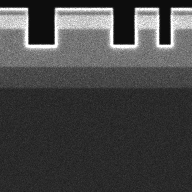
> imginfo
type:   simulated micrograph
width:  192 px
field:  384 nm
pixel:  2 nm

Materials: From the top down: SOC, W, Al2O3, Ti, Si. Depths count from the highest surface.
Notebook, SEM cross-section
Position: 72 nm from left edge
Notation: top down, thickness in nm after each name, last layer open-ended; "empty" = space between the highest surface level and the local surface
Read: empty 74, Al2O3 44, Ti 42, Si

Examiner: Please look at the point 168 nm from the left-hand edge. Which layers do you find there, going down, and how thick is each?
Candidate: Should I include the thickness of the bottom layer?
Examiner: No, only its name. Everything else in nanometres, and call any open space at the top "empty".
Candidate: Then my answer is SOC 14, W 28, Al2O3 76, Ti 42, Si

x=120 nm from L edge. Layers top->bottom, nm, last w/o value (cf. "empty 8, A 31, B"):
SOC 14, W 28, Al2O3 76, Ti 42, Si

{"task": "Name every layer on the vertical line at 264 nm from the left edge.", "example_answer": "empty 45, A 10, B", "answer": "empty 74, Al2O3 44, Ti 42, Si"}